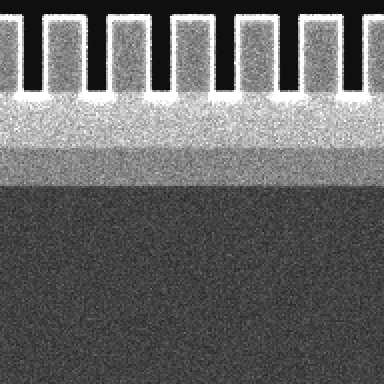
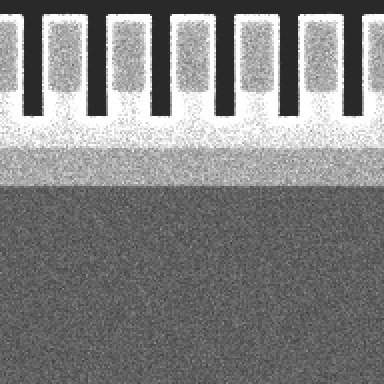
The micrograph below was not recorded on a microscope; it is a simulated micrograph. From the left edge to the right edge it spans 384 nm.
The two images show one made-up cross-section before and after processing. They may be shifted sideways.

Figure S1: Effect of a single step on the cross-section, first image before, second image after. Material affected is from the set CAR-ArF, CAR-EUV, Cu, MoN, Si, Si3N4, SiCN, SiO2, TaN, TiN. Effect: removed SiO2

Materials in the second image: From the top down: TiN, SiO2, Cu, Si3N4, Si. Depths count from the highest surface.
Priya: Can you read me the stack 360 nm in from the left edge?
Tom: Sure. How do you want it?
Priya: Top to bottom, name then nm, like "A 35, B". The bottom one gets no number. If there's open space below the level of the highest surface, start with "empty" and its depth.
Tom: empty 102, Cu 30, Si3N4 38, Si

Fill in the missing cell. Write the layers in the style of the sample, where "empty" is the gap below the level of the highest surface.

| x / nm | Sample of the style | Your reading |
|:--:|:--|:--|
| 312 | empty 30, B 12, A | TiN 76, SiO2 26, Cu 30, Si3N4 38, Si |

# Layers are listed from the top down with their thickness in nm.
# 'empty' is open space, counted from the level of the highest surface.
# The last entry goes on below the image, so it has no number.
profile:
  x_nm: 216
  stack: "empty 102, Cu 30, Si3N4 38, Si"